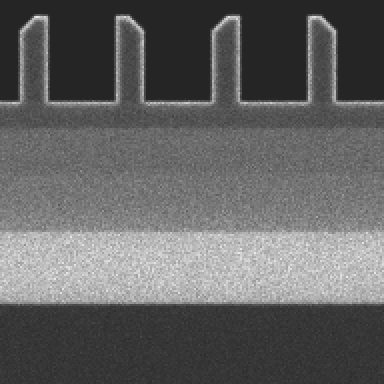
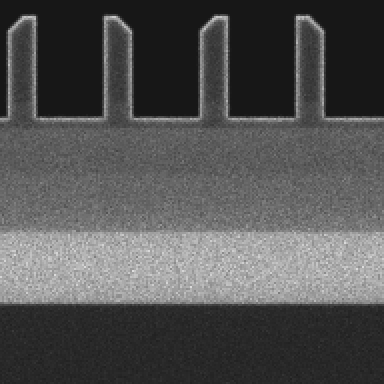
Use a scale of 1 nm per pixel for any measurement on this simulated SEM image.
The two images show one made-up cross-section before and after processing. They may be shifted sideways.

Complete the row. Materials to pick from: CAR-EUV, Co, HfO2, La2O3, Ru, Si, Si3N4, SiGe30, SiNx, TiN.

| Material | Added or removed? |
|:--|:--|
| TiN | removed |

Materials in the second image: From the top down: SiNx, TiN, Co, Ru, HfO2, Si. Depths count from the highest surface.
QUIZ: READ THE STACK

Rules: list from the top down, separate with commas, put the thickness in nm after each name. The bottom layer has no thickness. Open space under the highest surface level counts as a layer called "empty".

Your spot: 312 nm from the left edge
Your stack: empty 4, SiNx 82, TiN 26, Co 46, Ru 58, HfO2 72, Si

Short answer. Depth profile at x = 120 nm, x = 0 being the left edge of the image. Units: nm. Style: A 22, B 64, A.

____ empty 4, SiNx 82, TiN 26, Co 46, Ru 58, HfO2 72, Si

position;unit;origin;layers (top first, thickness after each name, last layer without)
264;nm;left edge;empty 102, TiN 10, Co 46, Ru 58, HfO2 72, Si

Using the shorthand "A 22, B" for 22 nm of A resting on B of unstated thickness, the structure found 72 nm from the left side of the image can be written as empty 102, TiN 10, Co 46, Ru 58, HfO2 72, Si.